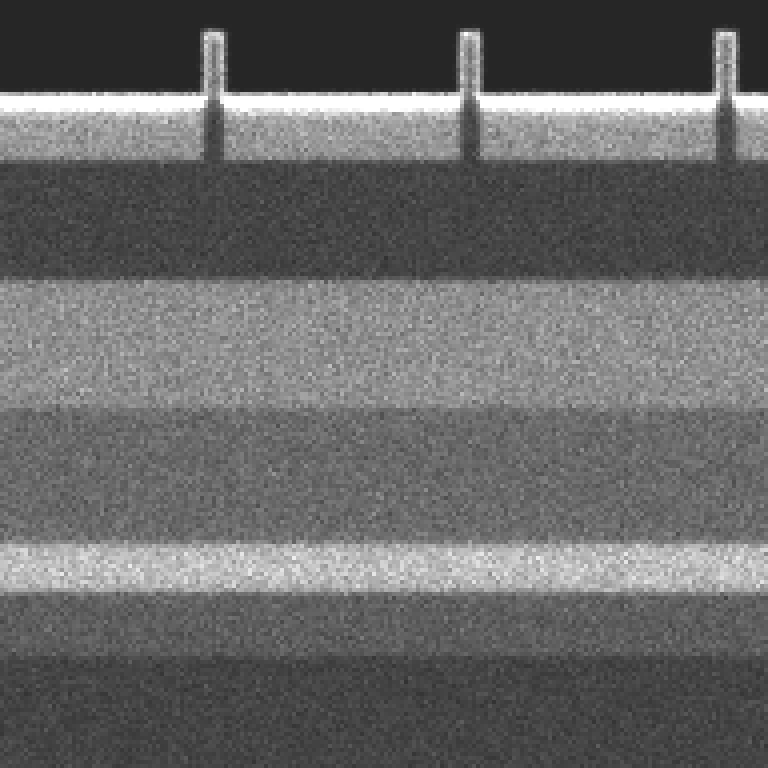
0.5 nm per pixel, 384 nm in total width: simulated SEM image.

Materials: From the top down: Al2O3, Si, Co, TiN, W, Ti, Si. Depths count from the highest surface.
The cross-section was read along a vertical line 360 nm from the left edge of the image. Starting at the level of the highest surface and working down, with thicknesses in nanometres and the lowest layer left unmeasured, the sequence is Si 124, Co 64, TiN 68, W 24, Ti 32, Si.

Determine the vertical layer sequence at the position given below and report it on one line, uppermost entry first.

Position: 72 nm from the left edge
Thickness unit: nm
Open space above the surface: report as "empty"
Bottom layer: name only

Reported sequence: empty 32, Al2O3 32, Si 60, Co 64, TiN 68, W 24, Ti 32, Si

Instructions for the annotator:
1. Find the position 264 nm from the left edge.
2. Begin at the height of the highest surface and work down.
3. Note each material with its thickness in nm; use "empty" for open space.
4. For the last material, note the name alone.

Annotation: empty 32, Al2O3 32, Si 60, Co 64, TiN 68, W 24, Ti 32, Si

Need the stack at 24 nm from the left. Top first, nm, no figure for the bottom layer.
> empty 32, Al2O3 32, Si 60, Co 64, TiN 68, W 24, Ti 32, Si